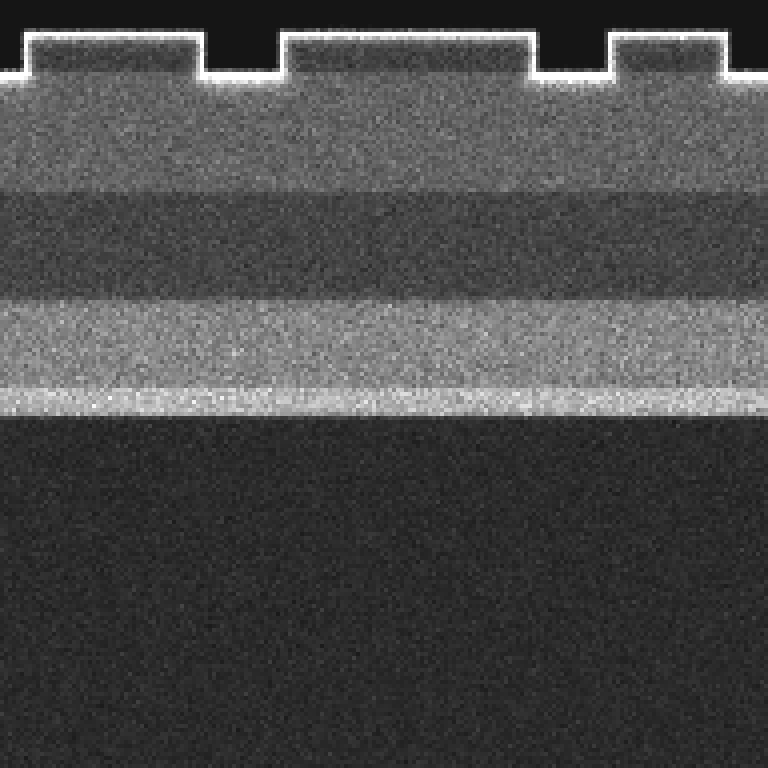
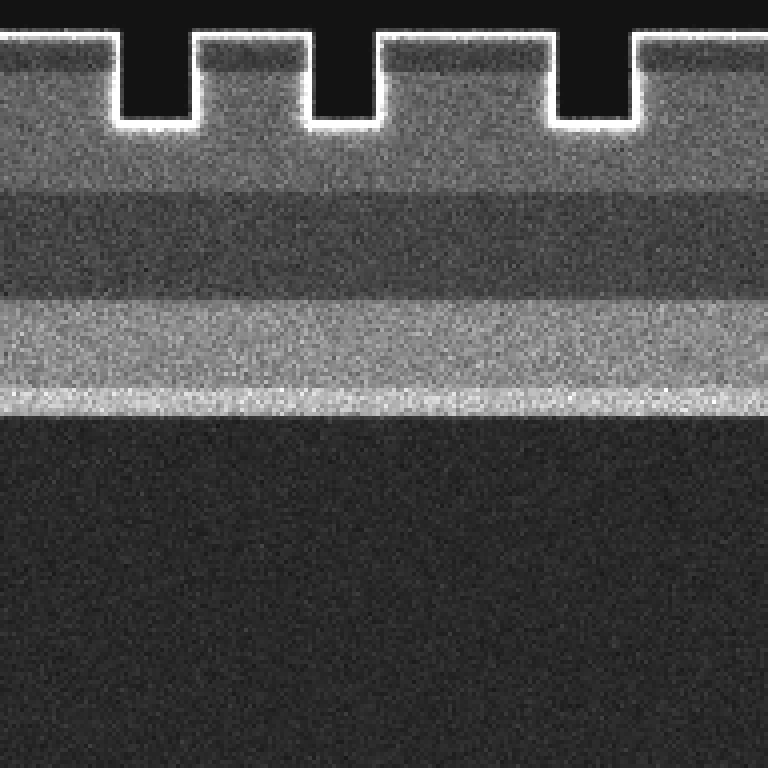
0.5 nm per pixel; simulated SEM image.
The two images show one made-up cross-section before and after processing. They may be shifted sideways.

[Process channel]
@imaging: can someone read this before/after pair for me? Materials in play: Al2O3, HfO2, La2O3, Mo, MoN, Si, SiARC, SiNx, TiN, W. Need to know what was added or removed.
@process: Al2O3 removed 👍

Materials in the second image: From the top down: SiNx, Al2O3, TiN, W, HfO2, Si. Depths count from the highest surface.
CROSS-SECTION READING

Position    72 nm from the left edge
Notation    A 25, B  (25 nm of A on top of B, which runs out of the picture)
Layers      empty 44, Al2O3 36, TiN 54, W 44, HfO2 14, Si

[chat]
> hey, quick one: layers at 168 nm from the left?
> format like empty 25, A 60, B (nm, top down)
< empty 44, Al2O3 36, TiN 54, W 44, HfO2 14, Si